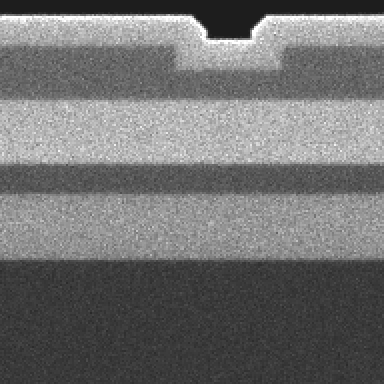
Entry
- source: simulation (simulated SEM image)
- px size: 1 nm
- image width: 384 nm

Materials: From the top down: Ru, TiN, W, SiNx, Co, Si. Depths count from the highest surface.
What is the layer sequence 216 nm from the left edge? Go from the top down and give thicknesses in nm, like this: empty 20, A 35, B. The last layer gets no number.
empty 24, Ru 30, TiN 30, W 64, SiNx 30, Co 66, Si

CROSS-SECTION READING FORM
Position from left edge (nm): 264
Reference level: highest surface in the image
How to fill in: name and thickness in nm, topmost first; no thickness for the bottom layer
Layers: empty 2, Ru 52, TiN 30, W 64, SiNx 30, Co 66, Si